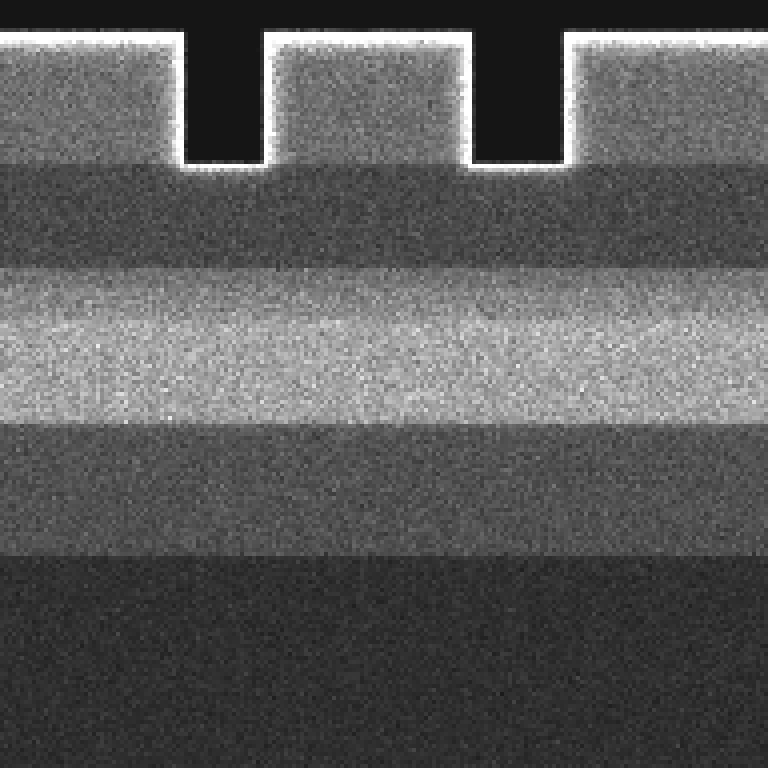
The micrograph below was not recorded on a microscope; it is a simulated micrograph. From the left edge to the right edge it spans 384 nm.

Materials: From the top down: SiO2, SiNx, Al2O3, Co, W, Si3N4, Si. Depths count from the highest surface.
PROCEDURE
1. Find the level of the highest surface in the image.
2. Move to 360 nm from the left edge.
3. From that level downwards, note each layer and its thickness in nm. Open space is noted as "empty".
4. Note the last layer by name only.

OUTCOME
SiO2 66, SiNx 52, Al2O3 10, Co 16, W 52, Si3N4 66, Si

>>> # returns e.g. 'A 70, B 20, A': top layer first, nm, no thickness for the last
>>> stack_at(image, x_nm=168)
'SiO2 66, SiNx 52, Al2O3 10, Co 16, W 52, Si3N4 66, Si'